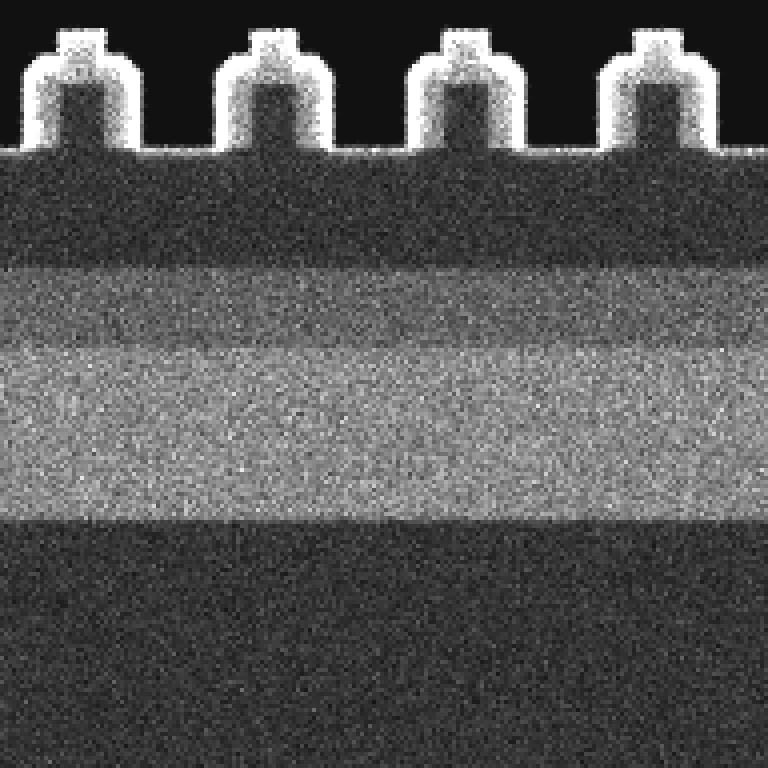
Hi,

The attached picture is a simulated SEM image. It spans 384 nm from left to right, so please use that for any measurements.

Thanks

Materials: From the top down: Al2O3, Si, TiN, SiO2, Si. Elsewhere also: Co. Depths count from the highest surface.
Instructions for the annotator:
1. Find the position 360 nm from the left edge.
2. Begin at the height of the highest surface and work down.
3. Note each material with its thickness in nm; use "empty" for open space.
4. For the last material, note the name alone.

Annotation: empty 58, Si 60, TiN 40, SiO2 86, Si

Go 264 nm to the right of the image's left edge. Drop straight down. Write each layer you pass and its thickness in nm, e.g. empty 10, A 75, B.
empty 58, Si 60, TiN 40, SiO2 86, Si